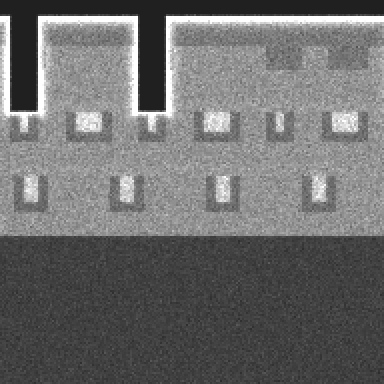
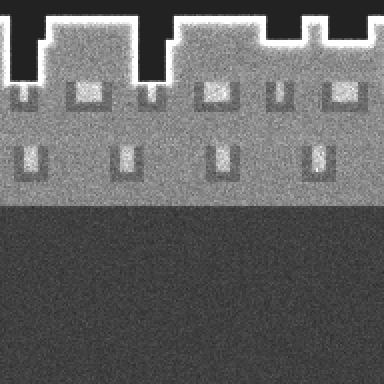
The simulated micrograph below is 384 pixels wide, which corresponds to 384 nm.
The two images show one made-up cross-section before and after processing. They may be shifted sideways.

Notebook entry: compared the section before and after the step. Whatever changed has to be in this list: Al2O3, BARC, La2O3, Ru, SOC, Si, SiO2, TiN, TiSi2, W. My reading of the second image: SOC removed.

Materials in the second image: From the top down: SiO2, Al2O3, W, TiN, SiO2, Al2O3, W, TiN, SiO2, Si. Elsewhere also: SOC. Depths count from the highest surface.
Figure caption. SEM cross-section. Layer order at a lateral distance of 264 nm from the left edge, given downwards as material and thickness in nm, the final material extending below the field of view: SiO2 56, Al2O3 10, SiO2 52, Al2O3 12, SiO2 60, Si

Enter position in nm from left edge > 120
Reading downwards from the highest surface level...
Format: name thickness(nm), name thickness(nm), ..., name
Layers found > SiO2 56, Al2O3 10, SiO2 52, Al2O3 12, W 26, TiN 10, SiO2 24, Si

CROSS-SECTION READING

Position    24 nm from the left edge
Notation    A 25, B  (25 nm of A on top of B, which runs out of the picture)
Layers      empty 66, W 20, TiN 10, SiO2 22, Al2O3 12, W 26, TiN 10, SiO2 24, Si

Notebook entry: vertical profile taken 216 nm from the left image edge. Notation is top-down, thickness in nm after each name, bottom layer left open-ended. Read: SiO2 56, Al2O3 10, W 20, TiN 10, SiO2 22, Al2O3 12, W 26, TiN 10, SiO2 24, Si